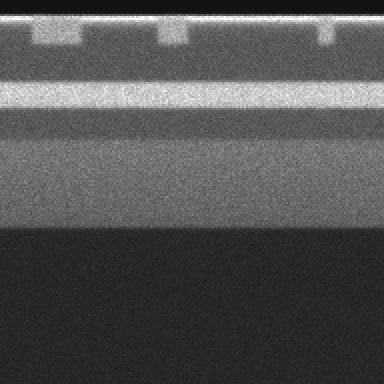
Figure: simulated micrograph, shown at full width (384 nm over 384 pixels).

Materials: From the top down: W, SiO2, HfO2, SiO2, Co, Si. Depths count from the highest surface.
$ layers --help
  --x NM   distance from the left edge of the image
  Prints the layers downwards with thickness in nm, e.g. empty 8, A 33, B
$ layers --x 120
SiO2 66, HfO2 26, SiO2 32, Co 88, Si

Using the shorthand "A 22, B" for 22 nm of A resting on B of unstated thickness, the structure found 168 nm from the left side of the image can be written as W 28, SiO2 38, HfO2 26, SiO2 32, Co 88, Si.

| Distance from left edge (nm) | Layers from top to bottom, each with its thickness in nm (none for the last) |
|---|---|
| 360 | SiO2 66, HfO2 26, SiO2 32, Co 88, Si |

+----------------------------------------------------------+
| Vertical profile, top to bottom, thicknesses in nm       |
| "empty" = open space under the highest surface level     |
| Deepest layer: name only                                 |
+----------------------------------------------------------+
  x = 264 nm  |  SiO2 66, HfO2 26, SiO2 32, Co 88, Si